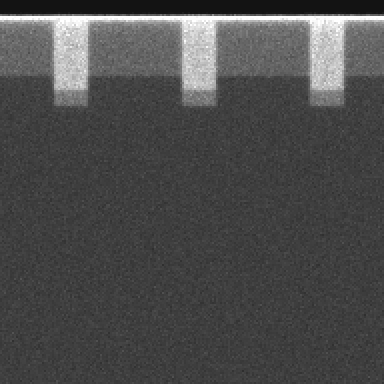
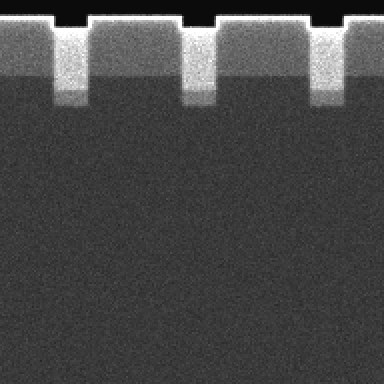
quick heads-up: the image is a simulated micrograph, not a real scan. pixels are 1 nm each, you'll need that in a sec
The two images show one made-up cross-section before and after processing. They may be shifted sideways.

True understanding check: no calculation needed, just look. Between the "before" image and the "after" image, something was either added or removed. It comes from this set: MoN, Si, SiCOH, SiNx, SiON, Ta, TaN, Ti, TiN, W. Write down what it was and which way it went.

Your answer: W (removed)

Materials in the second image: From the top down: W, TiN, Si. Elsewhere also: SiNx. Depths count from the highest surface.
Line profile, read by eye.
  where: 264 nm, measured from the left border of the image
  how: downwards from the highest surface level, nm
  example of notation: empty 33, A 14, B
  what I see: SiNx 60, Si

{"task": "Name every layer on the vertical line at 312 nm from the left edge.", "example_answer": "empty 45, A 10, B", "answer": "empty 12, W 62, TiN 16, Si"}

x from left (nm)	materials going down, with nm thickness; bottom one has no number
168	SiNx 60, Si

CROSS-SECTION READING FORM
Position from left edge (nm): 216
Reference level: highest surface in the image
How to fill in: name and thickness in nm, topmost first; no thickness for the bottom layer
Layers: SiNx 60, Si